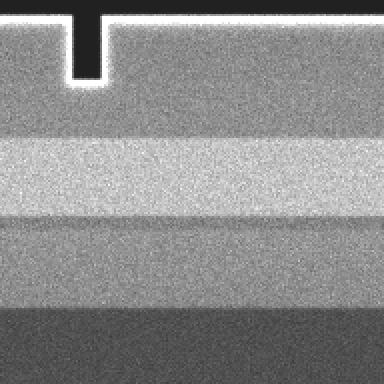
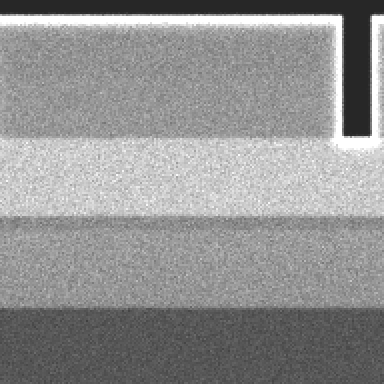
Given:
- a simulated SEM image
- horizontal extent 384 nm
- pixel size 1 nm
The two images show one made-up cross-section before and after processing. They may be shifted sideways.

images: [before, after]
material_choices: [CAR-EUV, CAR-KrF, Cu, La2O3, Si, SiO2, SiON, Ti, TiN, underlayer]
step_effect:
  removed: underlayer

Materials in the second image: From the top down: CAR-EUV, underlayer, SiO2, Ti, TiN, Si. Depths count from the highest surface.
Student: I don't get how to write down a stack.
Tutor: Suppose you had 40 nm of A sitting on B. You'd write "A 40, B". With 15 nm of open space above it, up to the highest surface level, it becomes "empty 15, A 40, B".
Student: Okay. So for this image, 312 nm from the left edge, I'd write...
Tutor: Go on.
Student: CAR-EUV 64, underlayer 58, SiO2 78, Ti 14, TiN 78, Si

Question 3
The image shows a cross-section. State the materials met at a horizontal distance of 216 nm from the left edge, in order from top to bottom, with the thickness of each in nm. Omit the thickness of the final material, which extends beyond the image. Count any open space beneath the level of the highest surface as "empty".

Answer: CAR-EUV 64, underlayer 58, SiO2 78, Ti 14, TiN 78, Si